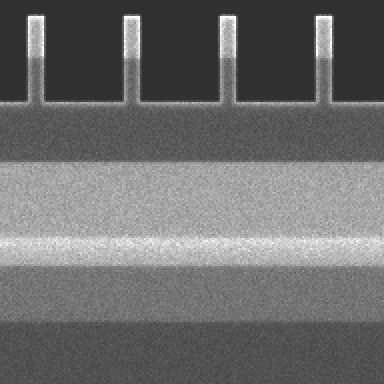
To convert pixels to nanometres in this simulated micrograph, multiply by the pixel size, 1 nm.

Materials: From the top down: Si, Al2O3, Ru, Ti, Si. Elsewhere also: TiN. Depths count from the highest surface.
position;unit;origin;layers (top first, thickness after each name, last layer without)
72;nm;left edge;empty 86, Si 60, Al2O3 76, Ru 28, Ti 56, Si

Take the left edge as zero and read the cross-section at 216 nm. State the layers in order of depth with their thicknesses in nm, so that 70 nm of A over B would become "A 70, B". empty 86, Si 60, Al2O3 76, Ru 28, Ti 56, Si